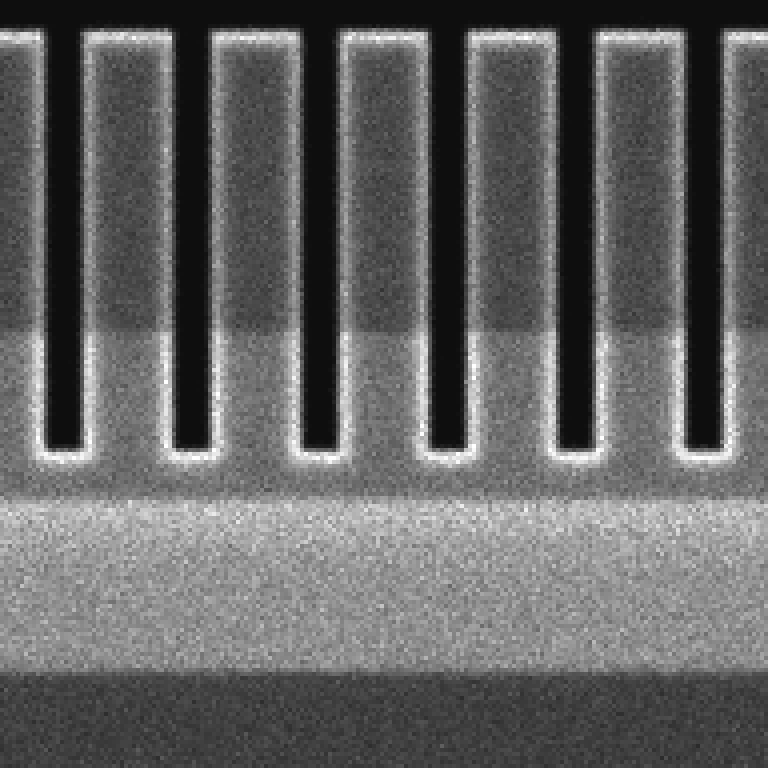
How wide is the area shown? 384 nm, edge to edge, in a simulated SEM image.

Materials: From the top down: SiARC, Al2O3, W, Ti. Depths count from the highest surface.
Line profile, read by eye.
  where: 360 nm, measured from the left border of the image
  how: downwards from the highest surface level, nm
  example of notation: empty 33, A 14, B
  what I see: empty 210, Al2O3 24, W 86, Ti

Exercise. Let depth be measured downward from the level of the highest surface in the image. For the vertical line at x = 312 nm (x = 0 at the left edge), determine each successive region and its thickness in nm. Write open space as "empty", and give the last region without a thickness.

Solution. SiARC 150, Al2O3 84, W 86, Ti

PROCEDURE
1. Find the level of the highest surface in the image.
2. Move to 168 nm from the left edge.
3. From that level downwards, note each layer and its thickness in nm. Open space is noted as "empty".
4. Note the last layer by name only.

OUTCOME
empty 210, Al2O3 24, W 86, Ti